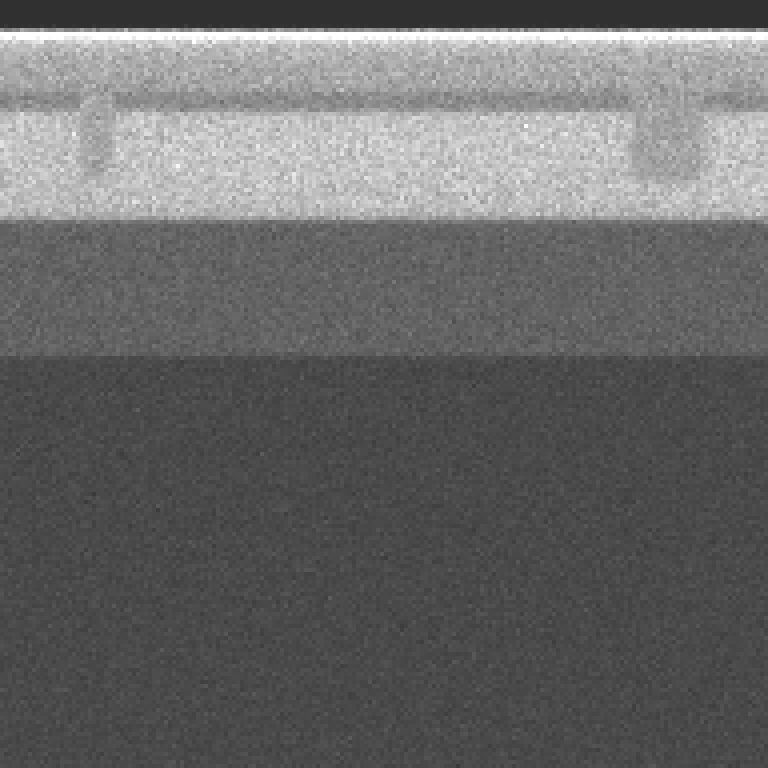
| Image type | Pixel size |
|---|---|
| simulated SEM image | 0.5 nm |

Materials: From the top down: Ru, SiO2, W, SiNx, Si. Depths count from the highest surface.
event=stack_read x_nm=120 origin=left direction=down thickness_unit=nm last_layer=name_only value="Ru 30, SiO2 10, W 54, SiNx 68, Si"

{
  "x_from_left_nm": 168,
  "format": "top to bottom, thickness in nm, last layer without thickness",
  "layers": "Ru 30, SiO2 10, W 54, SiNx 68, Si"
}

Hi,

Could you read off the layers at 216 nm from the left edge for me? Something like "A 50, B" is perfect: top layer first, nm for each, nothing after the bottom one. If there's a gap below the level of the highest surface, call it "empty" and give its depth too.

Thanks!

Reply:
Ru 30, SiO2 10, W 54, SiNx 68, Si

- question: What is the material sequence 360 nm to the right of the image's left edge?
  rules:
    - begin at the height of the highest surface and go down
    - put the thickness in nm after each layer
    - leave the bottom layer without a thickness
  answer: Ru 30, SiO2 10, W 54, SiNx 68, Si